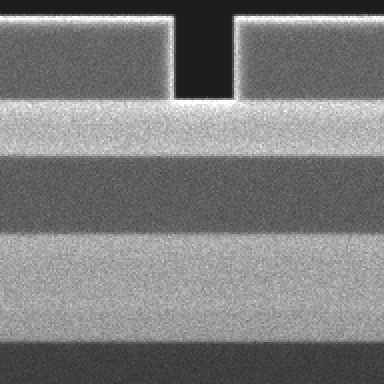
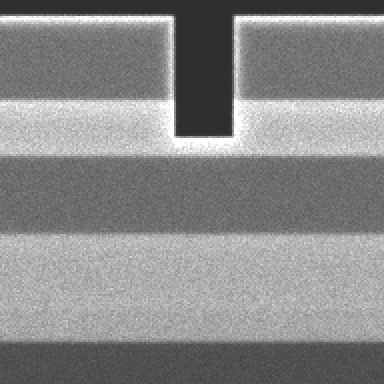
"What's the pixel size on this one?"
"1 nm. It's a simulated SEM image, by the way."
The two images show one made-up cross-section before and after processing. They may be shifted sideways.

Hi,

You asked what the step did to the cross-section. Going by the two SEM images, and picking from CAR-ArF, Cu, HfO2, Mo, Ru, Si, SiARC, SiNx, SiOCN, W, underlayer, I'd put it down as W, removed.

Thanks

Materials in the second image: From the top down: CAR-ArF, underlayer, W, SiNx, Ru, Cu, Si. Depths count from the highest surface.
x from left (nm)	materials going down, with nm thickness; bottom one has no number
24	CAR-ArF 62, underlayer 22, W 56, SiNx 78, Ru 76, Cu 32, Si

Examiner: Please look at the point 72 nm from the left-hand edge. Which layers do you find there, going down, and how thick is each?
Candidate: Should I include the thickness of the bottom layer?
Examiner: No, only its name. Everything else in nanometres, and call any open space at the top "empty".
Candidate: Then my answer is CAR-ArF 62, underlayer 22, W 56, SiNx 78, Ru 76, Cu 32, Si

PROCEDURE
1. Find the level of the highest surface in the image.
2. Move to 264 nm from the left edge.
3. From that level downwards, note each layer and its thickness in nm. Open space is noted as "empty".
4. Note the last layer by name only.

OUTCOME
CAR-ArF 62, underlayer 22, W 56, SiNx 78, Ru 76, Cu 32, Si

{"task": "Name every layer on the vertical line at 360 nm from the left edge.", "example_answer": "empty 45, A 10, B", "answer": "CAR-ArF 62, underlayer 22, W 56, SiNx 78, Ru 76, Cu 32, Si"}